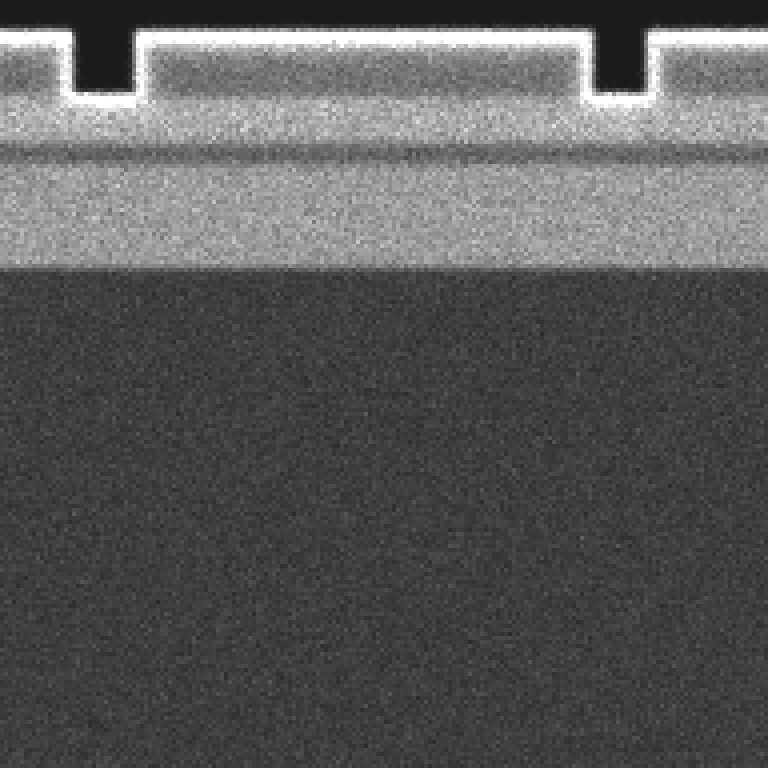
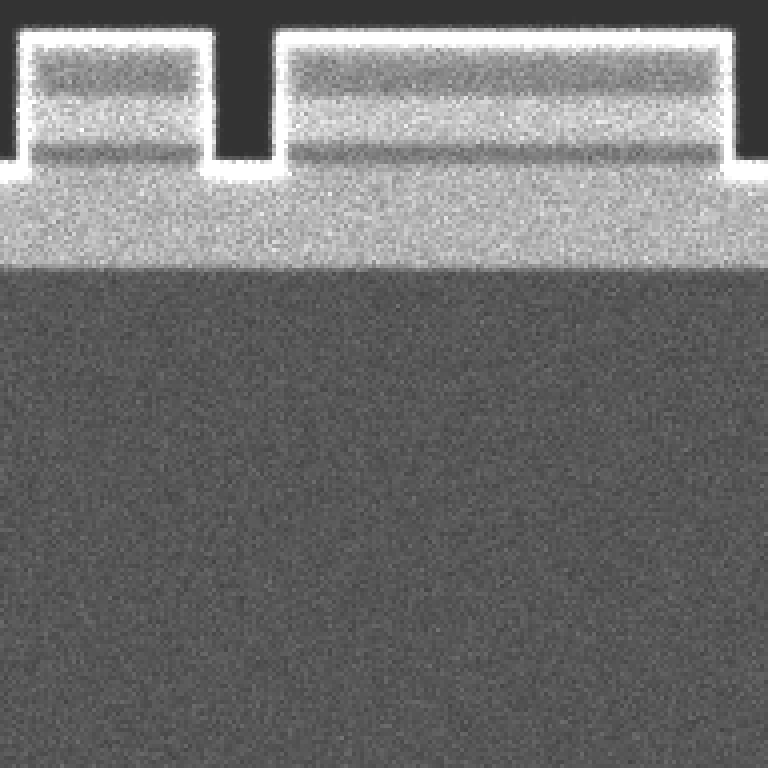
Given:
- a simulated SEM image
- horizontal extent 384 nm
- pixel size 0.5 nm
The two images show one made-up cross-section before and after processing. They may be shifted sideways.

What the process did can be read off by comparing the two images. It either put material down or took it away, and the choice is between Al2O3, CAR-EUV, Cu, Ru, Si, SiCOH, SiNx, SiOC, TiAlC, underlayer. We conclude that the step removed Ru and SiNx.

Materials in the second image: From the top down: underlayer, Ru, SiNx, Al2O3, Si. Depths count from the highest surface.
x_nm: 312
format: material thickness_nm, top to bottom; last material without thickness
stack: underlayer 32, Ru 24, SiNx 10, Al2O3 52, Si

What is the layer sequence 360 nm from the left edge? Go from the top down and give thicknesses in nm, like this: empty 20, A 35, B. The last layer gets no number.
underlayer 32, Ru 24, SiNx 10, Al2O3 52, Si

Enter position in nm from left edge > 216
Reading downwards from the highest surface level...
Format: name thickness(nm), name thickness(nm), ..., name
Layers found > underlayer 32, Ru 24, SiNx 10, Al2O3 52, Si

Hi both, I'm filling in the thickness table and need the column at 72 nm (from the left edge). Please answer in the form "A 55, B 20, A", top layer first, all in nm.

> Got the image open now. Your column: underlayer 32, Ru 24, SiNx 10, Al2O3 52, Si